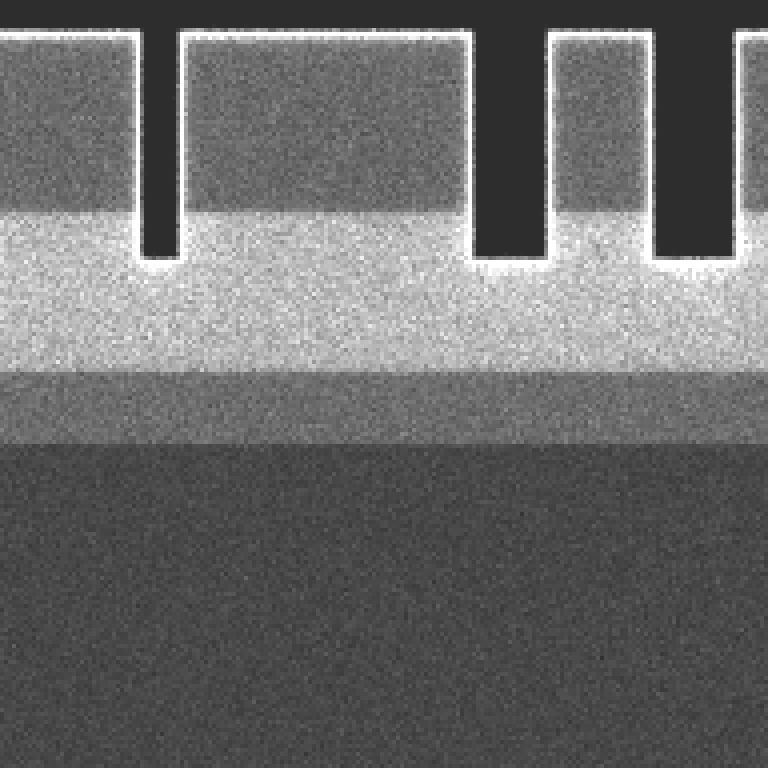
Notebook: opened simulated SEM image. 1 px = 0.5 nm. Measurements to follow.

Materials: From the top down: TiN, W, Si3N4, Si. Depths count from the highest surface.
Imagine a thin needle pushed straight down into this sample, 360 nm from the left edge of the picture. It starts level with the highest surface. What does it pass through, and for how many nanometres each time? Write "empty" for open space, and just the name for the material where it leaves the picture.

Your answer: empty 114, W 56, Si3N4 36, Si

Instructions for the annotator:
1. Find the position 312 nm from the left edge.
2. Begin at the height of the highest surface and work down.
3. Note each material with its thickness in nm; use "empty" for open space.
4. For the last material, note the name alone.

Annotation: TiN 90, W 80, Si3N4 36, Si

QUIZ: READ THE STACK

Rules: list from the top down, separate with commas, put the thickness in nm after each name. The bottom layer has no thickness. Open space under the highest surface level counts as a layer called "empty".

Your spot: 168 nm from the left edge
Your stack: TiN 90, W 80, Si3N4 36, Si